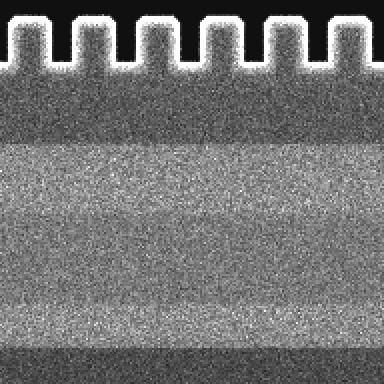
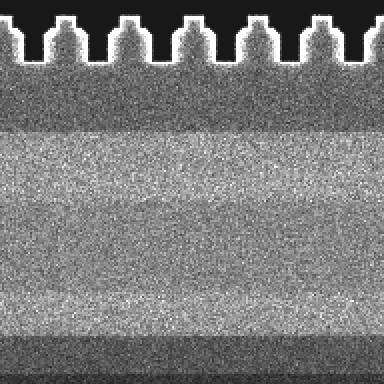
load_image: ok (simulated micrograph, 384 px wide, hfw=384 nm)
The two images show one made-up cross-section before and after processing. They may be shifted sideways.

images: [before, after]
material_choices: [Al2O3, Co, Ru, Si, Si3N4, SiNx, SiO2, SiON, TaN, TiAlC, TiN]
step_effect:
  removed: Al2O3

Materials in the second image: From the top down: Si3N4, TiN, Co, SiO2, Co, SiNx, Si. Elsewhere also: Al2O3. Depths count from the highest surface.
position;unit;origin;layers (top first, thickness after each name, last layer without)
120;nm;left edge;Si3N4 46, TiN 70, Co 70, SiO2 90, Co 44, SiNx 38, Si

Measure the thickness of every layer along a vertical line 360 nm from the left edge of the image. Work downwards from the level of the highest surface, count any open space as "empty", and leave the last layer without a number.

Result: empty 46, TiN 70, Co 70, SiO2 90, Co 44, SiNx 38, Si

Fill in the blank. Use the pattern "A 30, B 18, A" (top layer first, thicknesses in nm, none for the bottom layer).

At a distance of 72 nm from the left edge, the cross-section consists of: Si3N4 46, TiN 70, Co 70, SiO2 90, Co 44, SiNx 38, Si